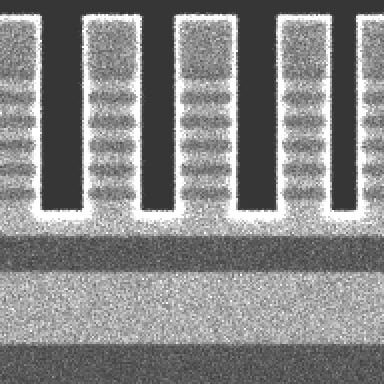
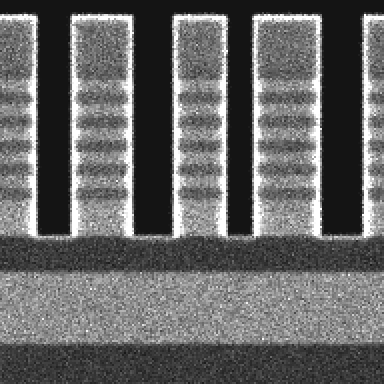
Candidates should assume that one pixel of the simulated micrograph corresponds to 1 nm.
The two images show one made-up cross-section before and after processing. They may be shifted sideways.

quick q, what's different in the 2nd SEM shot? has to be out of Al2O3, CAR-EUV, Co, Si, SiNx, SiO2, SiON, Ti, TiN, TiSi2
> Al2O3 removed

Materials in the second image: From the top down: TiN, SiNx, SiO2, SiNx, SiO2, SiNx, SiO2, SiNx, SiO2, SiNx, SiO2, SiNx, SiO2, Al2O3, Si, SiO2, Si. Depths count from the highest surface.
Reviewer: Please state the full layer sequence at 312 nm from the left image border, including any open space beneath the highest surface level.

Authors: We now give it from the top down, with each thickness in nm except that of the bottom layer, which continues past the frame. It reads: TiN 52, SiNx 12, SiO2 12, SiNx 12, SiO2 12, SiNx 12, SiO2 12, SiNx 12, SiO2 12, SiNx 12, SiO2 12, SiNx 12, SiO2 12, Al2O3 24, Si 36, SiO2 72, Si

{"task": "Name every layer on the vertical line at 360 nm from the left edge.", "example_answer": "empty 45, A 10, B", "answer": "empty 220, Si 36, SiO2 72, Si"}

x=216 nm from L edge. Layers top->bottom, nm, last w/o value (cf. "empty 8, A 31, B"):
TiN 52, SiNx 12, SiO2 12, SiNx 12, SiO2 12, SiNx 12, SiO2 12, SiNx 12, SiO2 12, SiNx 12, SiO2 12, SiNx 12, SiO2 12, Al2O3 24, Si 36, SiO2 72, Si